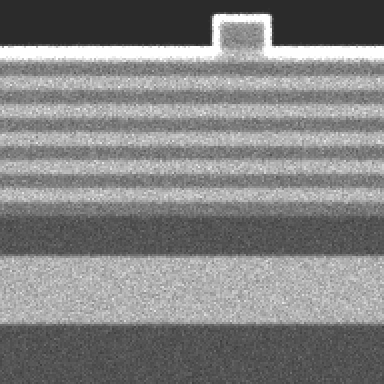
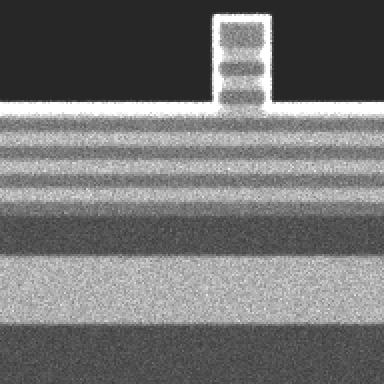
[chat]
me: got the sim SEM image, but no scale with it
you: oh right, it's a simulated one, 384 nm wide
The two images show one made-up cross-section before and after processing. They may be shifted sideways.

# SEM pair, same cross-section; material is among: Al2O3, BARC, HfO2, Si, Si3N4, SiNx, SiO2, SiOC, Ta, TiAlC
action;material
removed;Al2O3 and SiNx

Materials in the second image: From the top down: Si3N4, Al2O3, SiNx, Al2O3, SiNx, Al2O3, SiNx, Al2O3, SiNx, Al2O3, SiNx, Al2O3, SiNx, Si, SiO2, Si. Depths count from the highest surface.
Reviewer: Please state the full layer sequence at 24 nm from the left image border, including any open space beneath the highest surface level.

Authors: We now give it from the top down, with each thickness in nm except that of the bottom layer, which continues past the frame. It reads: empty 88, Al2O3 14, SiNx 14, Al2O3 14, SiNx 14, Al2O3 14, SiNx 14, Al2O3 14, SiNx 14, Si 40, SiO2 68, Si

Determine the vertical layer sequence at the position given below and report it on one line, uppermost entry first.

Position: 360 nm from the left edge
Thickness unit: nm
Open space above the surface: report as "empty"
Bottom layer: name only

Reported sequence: empty 88, Al2O3 14, SiNx 14, Al2O3 14, SiNx 14, Al2O3 14, SiNx 14, Al2O3 14, SiNx 14, Si 40, SiO2 68, Si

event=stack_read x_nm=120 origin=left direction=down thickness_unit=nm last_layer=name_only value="empty 88, Al2O3 14, SiNx 14, Al2O3 14, SiNx 14, Al2O3 14, SiNx 14, Al2O3 14, SiNx 14, Si 40, SiO2 68, Si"